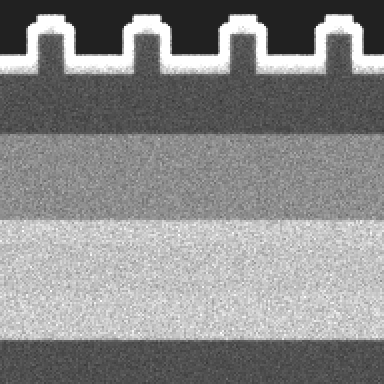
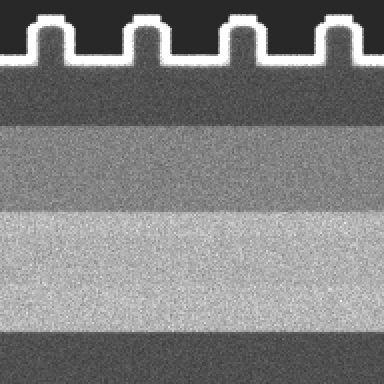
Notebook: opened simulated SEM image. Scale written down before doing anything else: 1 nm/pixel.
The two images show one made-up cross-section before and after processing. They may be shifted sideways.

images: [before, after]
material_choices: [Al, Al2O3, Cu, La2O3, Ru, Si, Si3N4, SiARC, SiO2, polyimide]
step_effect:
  removed: SiO2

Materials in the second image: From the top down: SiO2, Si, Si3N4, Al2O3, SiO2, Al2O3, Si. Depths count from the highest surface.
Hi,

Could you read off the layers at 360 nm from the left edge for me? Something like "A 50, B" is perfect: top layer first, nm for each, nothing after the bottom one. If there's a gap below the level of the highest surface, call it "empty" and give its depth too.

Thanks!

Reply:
empty 12, SiO2 38, Si 60, Si3N4 86, Al2O3 24, SiO2 48, Al2O3 48, Si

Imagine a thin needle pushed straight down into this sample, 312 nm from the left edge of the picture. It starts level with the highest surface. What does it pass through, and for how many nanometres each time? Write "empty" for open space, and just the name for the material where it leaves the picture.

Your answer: empty 40, SiO2 10, Si 60, Si3N4 86, Al2O3 24, SiO2 48, Al2O3 48, Si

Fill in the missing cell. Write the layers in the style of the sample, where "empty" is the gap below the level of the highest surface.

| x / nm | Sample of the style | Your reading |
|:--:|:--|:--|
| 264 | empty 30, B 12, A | empty 12, SiO2 38, Si 60, Si3N4 86, Al2O3 24, SiO2 48, Al2O3 48, Si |